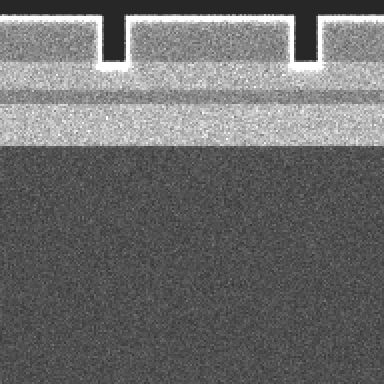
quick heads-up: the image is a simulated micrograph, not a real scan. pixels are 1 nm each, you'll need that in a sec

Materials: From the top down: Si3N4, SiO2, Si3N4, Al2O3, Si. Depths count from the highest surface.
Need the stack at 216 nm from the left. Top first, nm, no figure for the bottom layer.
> Si3N4 46, SiO2 28, Si3N4 14, Al2O3 42, Si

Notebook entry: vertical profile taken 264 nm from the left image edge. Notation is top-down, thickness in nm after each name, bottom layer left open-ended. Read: Si3N4 46, SiO2 28, Si3N4 14, Al2O3 42, Si